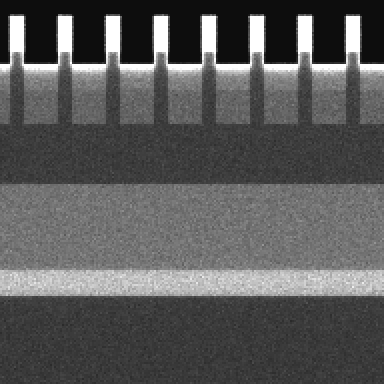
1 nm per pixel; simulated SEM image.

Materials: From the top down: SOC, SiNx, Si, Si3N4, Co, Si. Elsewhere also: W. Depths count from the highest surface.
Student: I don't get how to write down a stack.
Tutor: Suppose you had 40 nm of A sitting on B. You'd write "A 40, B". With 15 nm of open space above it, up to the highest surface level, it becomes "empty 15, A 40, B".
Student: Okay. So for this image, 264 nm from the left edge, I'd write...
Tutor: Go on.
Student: empty 48, SOC 26, SiNx 34, Si 60, Si3N4 86, Co 26, Si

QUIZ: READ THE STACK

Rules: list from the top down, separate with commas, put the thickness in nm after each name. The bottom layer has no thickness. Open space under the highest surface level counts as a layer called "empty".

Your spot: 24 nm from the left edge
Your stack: empty 48, SOC 26, SiNx 34, Si 60, Si3N4 86, Co 26, Si